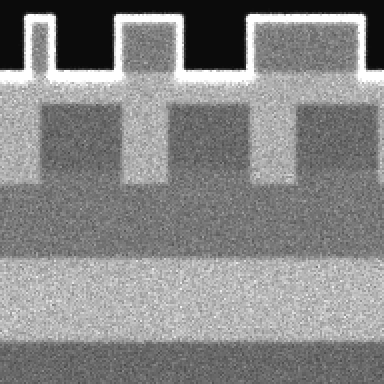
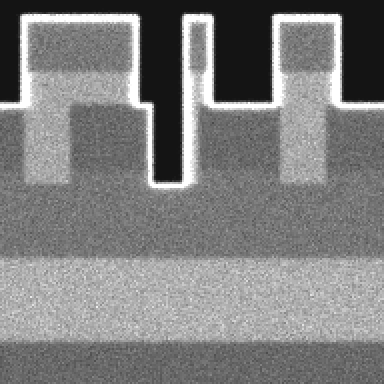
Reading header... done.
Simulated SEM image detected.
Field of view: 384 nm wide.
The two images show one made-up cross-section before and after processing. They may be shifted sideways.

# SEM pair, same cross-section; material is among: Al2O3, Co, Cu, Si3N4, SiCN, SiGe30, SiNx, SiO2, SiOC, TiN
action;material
removed;SiO2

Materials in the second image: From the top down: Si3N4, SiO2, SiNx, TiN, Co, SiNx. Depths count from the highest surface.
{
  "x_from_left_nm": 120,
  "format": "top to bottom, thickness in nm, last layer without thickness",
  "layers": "Si3N4 56, SiO2 32, SiNx 66, TiN 88, Co 84, SiNx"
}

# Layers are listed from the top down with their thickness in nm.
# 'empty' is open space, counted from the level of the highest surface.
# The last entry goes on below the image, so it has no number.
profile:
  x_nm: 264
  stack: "empty 88, SiNx 66, TiN 88, Co 84, SiNx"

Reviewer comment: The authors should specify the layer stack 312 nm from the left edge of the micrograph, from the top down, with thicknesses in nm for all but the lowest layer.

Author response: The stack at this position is Si3N4 56, SiO2 112, TiN 74, Co 84, SiNx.